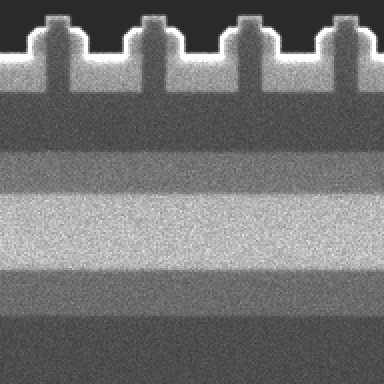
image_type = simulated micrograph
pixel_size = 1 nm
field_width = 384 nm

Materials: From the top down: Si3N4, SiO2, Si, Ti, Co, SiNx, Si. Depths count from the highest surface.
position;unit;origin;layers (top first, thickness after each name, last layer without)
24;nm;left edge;empty 38, SiO2 38, Si 60, Ti 42, Co 76, SiNx 46, Si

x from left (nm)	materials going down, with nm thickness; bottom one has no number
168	empty 12, Si3N4 26, SiO2 38, Si 60, Ti 42, Co 76, SiNx 46, Si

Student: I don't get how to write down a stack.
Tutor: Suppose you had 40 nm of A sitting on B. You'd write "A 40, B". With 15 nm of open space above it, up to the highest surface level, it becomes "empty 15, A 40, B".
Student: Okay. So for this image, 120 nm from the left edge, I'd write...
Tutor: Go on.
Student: empty 38, SiO2 38, Si 60, Ti 42, Co 76, SiNx 46, Si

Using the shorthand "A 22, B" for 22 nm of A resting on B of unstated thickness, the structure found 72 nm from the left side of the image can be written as empty 12, Si3N4 26, SiO2 38, Si 60, Ti 42, Co 76, SiNx 46, Si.